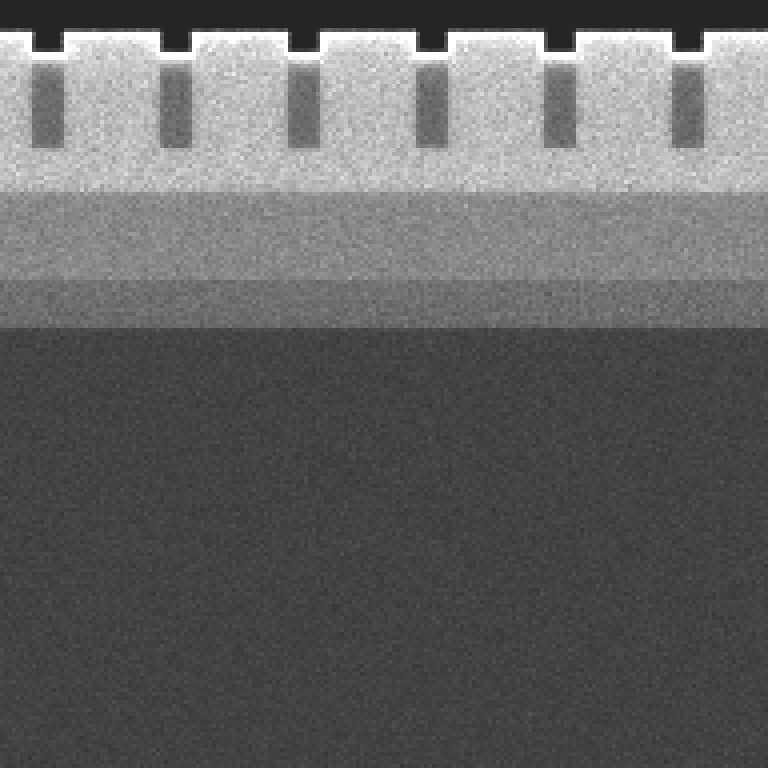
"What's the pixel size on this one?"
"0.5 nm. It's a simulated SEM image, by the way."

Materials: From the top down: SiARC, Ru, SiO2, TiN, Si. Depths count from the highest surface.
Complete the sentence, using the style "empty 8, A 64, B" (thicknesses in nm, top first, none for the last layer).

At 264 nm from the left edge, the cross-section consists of Ru 80, SiO2 44, TiN 24, Si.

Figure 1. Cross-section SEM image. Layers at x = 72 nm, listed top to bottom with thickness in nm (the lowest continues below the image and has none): Ru 80, SiO2 44, TiN 24, Si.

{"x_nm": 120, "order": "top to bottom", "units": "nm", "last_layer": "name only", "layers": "Ru 80, SiO2 44, TiN 24, Si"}